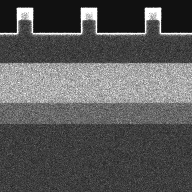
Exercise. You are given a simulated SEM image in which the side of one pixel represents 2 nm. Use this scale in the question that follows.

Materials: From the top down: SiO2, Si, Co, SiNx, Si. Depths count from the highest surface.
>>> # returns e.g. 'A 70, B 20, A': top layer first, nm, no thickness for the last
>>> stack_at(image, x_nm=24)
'empty 50, Si 60, Co 80, SiNx 42, Si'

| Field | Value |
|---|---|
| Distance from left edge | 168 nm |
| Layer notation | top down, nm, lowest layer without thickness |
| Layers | SiO2 24, Si 86, Co 80, SiNx 42, Si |